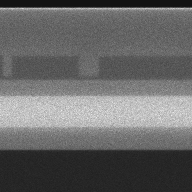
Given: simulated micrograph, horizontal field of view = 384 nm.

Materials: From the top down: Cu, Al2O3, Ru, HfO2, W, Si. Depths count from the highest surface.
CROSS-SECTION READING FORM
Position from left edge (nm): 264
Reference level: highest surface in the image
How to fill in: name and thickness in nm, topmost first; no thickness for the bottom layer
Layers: Cu 96, Al2O3 48, Ru 32, HfO2 62, W 46, Si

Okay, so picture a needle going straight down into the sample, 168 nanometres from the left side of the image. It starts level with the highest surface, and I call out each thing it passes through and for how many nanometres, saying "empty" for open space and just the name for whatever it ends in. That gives Cu 136, Al2O3 8, Ru 32, HfO2 62, W 46, Si